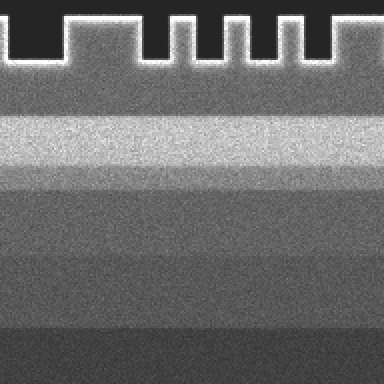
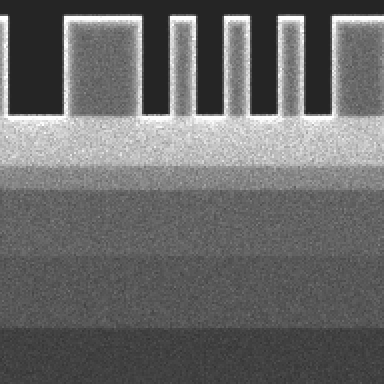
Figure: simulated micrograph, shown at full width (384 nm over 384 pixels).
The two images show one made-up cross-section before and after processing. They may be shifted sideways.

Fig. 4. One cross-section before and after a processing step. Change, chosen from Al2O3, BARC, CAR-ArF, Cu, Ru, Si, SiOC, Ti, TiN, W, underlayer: underlayer removed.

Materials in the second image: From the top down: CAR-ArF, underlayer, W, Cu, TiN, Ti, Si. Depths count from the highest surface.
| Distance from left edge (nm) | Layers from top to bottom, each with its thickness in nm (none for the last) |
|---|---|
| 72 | CAR-ArF 44, underlayer 56, W 50, Cu 24, TiN 66, Ti 72, Si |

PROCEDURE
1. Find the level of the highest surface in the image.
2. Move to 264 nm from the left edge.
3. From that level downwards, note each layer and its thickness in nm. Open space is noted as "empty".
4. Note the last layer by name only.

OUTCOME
empty 100, W 50, Cu 24, TiN 66, Ti 72, Si